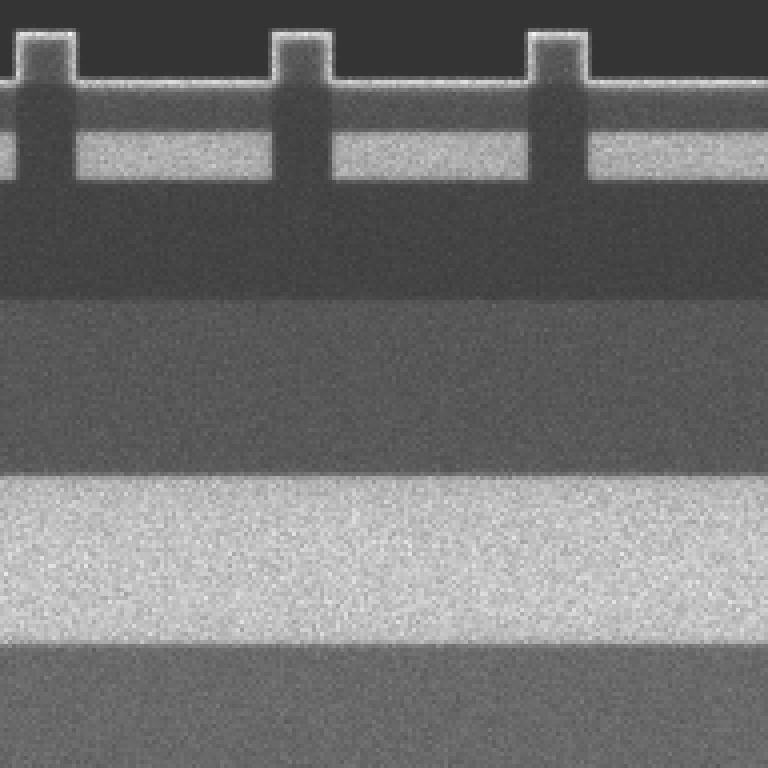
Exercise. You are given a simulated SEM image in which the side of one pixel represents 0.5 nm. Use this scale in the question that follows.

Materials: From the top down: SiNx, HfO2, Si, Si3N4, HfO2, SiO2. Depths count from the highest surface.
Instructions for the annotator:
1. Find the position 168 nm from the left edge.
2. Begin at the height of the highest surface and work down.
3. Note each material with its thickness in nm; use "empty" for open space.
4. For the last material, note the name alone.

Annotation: empty 24, SiNx 26, HfO2 24, Si 60, Si3N4 88, HfO2 84, SiO2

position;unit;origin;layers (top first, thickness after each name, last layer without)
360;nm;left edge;empty 24, SiNx 26, HfO2 24, Si 60, Si3N4 88, HfO2 84, SiO2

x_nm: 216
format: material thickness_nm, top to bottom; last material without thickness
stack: empty 24, SiNx 26, HfO2 24, Si 60, Si3N4 88, HfO2 84, SiO2